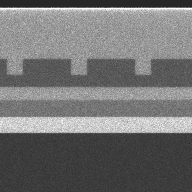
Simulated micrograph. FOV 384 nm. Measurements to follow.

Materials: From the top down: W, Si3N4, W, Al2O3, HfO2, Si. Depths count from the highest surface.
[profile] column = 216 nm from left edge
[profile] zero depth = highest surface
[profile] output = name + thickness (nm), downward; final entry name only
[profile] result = W 102, Si3N4 56, W 26, Al2O3 34, HfO2 32, Si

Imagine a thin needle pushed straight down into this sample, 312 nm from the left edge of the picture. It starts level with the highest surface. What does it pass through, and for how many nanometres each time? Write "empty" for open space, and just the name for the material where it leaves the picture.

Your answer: W 102, Si3N4 56, W 26, Al2O3 34, HfO2 32, Si